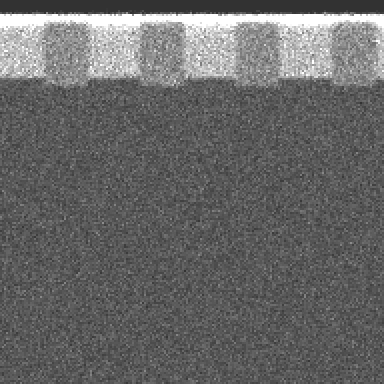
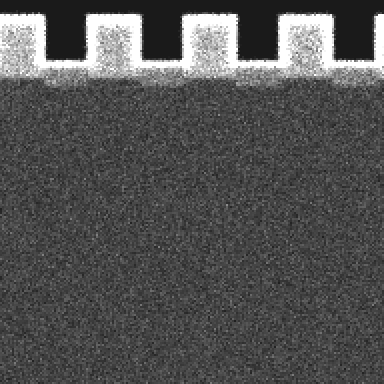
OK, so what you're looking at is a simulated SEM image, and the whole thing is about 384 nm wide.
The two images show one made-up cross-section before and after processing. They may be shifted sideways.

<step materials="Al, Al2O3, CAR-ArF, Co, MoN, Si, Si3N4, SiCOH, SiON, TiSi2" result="removed Si3N4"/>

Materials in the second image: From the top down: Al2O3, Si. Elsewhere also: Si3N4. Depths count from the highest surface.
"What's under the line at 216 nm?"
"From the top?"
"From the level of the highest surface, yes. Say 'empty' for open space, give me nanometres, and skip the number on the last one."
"Al2O3 62, Si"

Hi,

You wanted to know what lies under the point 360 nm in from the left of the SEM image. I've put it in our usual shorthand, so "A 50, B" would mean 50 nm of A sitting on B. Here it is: empty 46, Si3N4 24, Si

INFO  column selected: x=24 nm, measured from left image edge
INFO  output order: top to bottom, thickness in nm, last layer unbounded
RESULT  Al2O3 62, Si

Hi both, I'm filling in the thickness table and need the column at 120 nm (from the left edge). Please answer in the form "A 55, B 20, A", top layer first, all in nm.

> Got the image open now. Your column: Al2O3 62, Si